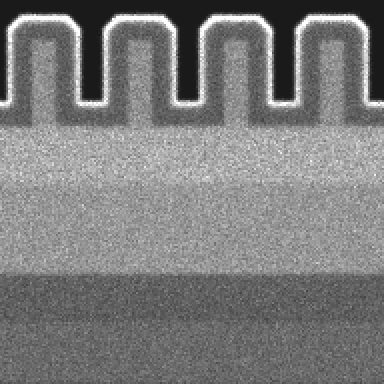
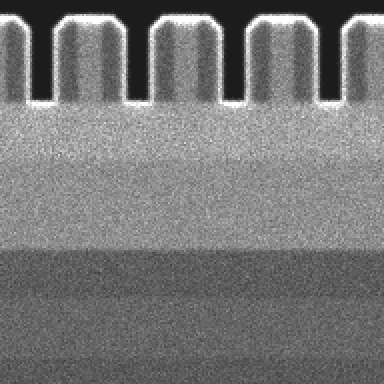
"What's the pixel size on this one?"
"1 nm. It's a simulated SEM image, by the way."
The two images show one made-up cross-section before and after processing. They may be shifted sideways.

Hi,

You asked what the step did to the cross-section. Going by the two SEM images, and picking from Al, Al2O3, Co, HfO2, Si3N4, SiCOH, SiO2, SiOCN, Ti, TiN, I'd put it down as SiOCN, removed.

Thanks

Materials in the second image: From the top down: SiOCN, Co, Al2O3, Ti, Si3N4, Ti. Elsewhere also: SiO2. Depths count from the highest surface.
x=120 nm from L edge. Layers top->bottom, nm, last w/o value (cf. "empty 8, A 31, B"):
empty 8, SiOCN 78, Co 58, Al2O3 90, Ti 48, Si3N4 60, Ti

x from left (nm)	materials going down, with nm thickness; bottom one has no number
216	empty 8, SiOCN 78, Co 58, Al2O3 90, Ti 48, Si3N4 60, Ti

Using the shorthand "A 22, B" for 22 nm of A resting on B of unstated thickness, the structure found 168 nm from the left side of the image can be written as SiOCN 86, Co 58, Al2O3 90, Ti 48, Si3N4 60, Ti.